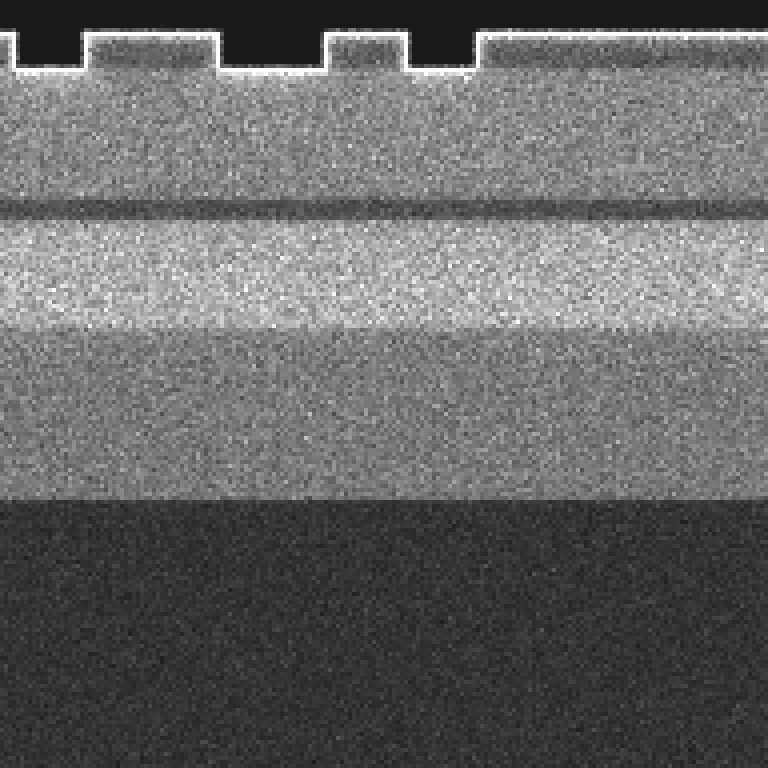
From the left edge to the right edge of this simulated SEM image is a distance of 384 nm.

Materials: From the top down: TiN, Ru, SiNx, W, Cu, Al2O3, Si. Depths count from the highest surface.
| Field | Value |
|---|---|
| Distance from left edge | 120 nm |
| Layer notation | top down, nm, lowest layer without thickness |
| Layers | empty 18, Ru 66, SiNx 10, W 54, Cu 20, Al2O3 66, Si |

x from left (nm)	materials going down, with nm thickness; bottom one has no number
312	TiN 18, Ru 66, SiNx 10, W 54, Cu 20, Al2O3 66, Si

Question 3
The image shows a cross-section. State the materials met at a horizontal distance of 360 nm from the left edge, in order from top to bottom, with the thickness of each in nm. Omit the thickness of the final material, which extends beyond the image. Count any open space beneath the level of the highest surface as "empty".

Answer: TiN 18, Ru 66, SiNx 10, W 54, Cu 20, Al2O3 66, Si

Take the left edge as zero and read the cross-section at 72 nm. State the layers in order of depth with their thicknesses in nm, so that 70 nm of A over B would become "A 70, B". TiN 18, Ru 66, SiNx 10, W 54, Cu 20, Al2O3 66, Si